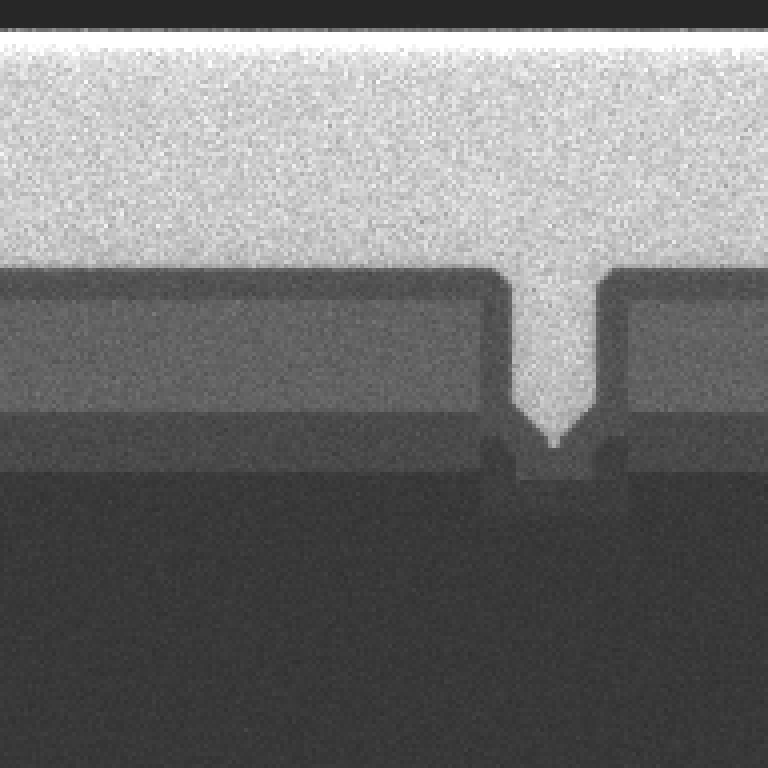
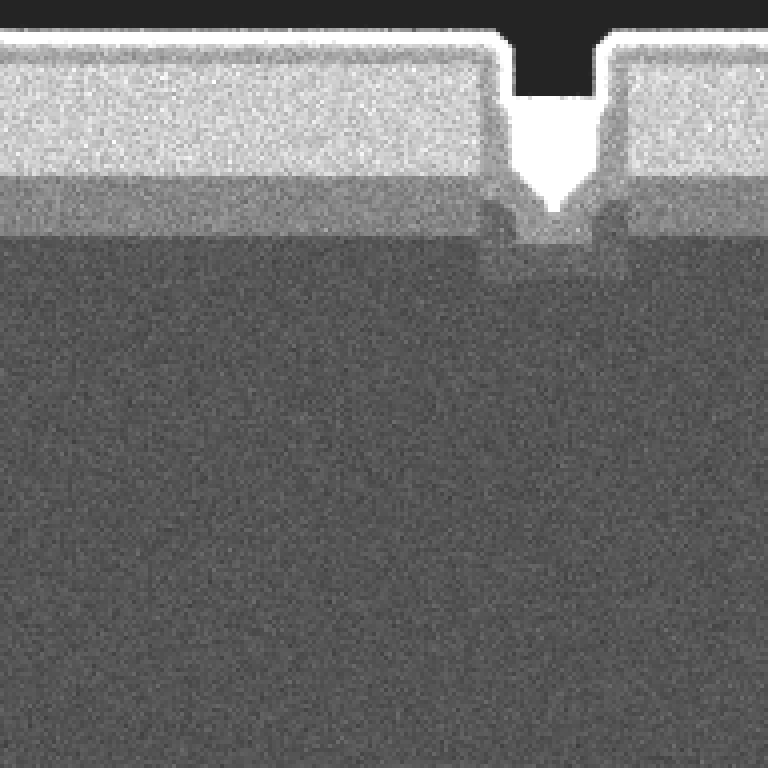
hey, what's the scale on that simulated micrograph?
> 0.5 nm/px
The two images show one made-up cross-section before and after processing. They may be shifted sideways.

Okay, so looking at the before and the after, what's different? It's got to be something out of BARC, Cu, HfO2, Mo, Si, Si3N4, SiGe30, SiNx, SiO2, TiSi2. HfO2, removed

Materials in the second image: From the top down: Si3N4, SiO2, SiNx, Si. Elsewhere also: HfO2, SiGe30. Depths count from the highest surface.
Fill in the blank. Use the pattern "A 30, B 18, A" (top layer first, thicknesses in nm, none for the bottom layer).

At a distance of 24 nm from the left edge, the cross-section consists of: Si3N4 16, SiO2 56, SiNx 30, Si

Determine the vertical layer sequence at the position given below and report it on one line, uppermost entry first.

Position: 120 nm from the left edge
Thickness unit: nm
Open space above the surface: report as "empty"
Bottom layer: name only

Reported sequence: Si3N4 16, SiO2 56, SiNx 30, Si